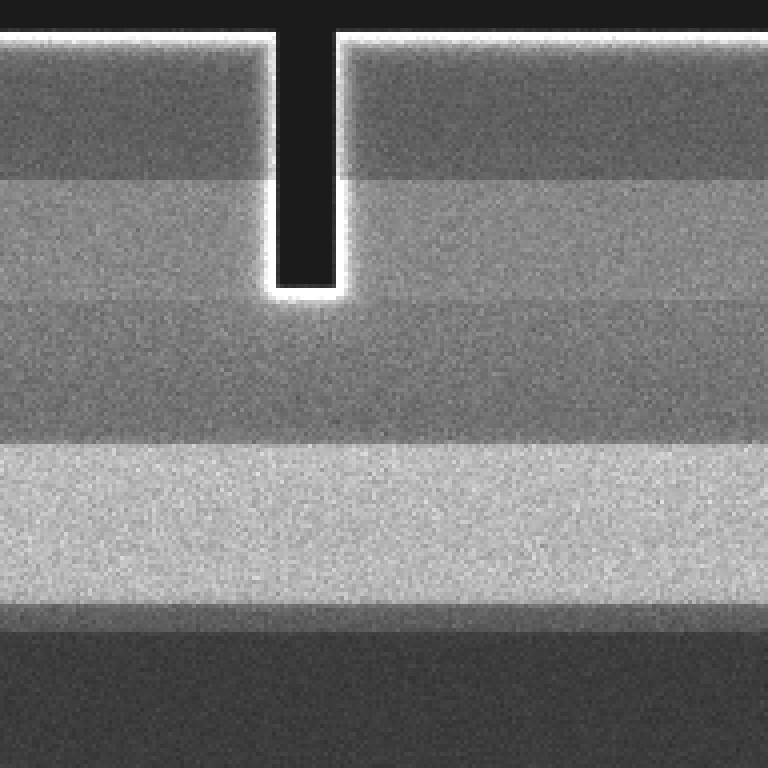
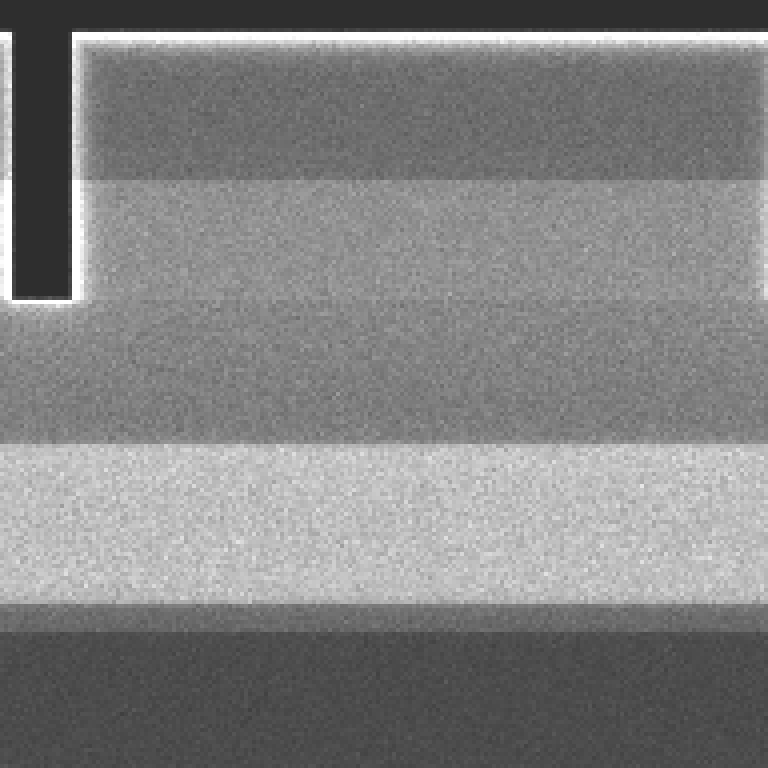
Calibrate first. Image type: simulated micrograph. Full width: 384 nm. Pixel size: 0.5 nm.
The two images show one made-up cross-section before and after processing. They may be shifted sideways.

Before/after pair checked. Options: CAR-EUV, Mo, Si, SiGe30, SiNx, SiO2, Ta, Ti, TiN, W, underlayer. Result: removed SiO2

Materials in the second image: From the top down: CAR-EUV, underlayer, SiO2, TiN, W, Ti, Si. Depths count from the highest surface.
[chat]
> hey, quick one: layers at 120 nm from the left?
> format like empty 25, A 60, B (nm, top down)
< CAR-EUV 58, underlayer 16, SiO2 60, TiN 72, W 80, Ti 14, Si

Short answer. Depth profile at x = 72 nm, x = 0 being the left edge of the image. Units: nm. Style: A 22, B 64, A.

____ CAR-EUV 58, underlayer 16, SiO2 60, TiN 72, W 80, Ti 14, Si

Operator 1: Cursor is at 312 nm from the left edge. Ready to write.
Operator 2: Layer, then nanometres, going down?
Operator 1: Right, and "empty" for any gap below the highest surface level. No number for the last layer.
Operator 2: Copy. CAR-EUV 58, underlayer 16, SiO2 60, TiN 72, W 80, Ti 14, Si